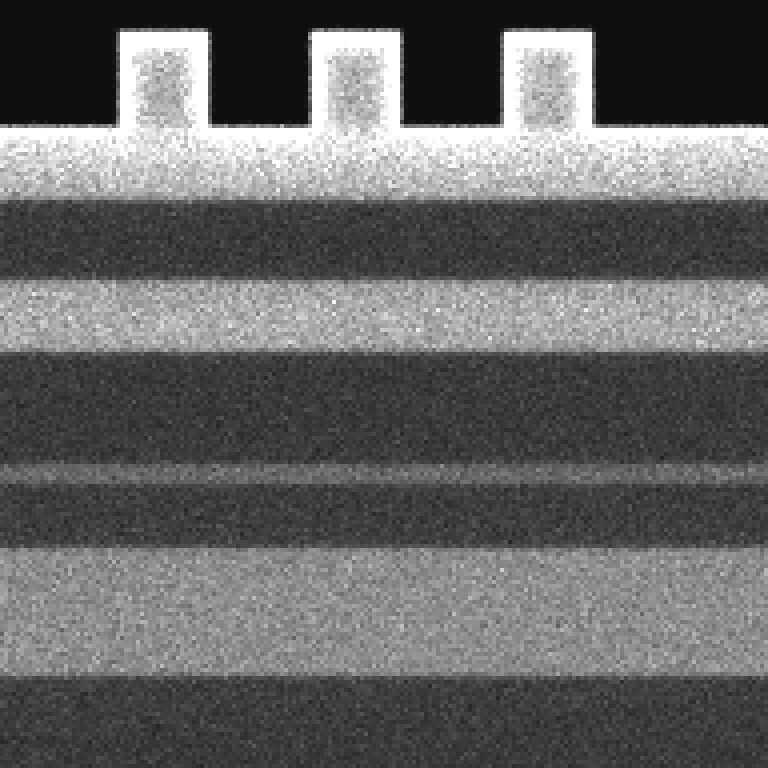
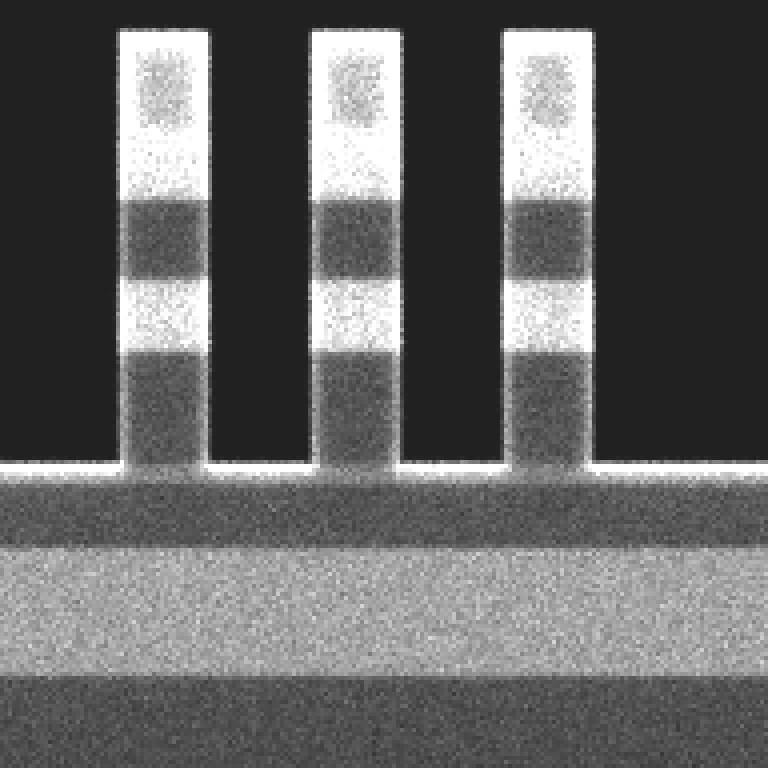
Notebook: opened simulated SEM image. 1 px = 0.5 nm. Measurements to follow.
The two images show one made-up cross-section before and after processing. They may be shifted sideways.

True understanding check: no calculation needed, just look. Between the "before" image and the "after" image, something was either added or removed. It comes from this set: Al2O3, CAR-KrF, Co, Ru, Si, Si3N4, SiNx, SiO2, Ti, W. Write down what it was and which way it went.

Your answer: Co and Si (removed)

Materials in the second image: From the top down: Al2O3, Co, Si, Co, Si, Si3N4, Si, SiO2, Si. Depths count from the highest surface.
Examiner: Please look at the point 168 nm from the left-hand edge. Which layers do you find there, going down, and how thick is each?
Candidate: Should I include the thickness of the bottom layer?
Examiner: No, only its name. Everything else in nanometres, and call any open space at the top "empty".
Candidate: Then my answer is Al2O3 48, Co 36, Si 40, Co 36, Si 56, Si3N4 10, Si 32, SiO2 64, Si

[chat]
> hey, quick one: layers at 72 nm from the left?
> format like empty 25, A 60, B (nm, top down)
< Al2O3 48, Co 36, Si 40, Co 36, Si 56, Si3N4 10, Si 32, SiO2 64, Si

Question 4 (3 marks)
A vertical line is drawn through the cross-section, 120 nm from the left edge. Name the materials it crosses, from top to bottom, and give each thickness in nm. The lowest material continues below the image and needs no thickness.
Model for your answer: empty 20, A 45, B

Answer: empty 216, Si3N4 10, Si 32, SiO2 64, Si